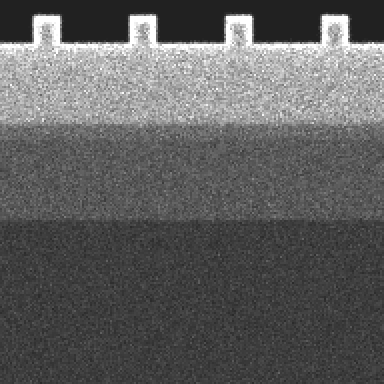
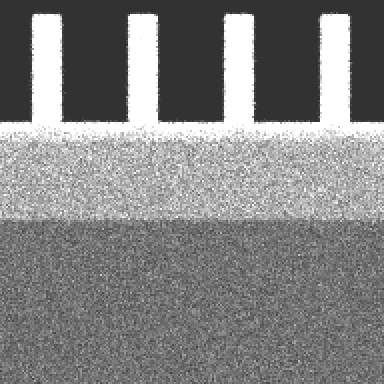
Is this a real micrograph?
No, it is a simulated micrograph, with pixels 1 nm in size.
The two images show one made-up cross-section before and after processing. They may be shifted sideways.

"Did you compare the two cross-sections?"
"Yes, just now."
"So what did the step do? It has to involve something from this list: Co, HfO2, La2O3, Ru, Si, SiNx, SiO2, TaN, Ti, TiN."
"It removed Ru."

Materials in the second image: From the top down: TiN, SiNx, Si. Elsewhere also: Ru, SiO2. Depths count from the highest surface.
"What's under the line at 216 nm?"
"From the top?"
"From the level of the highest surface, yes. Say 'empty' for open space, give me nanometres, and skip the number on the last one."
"empty 108, TiN 16, SiNx 80, Si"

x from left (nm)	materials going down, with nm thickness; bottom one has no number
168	empty 108, TiN 16, SiNx 80, Si